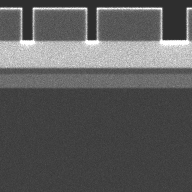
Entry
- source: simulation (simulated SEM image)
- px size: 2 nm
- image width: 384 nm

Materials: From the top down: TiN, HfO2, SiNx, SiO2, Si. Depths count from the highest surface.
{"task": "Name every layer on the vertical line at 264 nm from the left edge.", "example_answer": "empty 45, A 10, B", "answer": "TiN 66, HfO2 54, SiNx 12, SiO2 28, Si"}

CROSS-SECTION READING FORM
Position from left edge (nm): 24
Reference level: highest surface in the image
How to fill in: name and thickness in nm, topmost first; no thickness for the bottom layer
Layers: TiN 66, HfO2 54, SiNx 12, SiO2 28, Si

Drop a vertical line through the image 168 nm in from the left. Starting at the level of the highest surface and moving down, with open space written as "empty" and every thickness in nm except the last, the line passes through TiN 66, HfO2 54, SiNx 12, SiO2 28, Si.